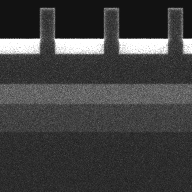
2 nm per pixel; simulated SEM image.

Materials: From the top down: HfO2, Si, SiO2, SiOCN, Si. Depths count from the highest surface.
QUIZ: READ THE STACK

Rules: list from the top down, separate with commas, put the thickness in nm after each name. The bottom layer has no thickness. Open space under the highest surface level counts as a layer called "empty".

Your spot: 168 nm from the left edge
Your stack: empty 62, HfO2 30, Si 60, SiO2 40, SiOCN 56, Si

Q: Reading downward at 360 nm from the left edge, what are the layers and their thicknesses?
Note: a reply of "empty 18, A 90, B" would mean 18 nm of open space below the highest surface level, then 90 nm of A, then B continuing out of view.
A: Si 152, SiO2 40, SiOCN 56, Si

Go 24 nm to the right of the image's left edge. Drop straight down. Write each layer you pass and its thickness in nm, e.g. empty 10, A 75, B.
empty 62, HfO2 30, Si 60, SiO2 40, SiOCN 56, Si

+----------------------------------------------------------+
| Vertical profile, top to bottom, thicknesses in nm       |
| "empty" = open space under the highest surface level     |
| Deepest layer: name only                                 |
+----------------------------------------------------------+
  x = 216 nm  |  Si 152, SiO2 40, SiOCN 56, Si